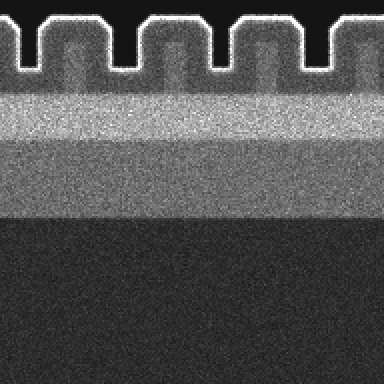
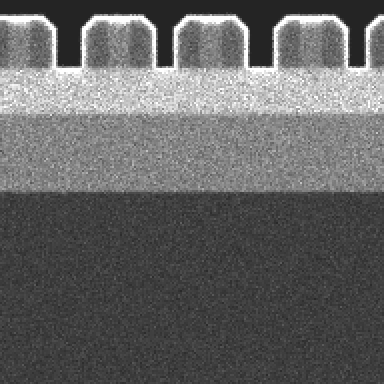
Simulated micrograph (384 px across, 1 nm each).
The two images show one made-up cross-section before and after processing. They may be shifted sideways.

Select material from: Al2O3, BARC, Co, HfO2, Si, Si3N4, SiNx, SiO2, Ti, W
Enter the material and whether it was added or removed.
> Si3N4 / removed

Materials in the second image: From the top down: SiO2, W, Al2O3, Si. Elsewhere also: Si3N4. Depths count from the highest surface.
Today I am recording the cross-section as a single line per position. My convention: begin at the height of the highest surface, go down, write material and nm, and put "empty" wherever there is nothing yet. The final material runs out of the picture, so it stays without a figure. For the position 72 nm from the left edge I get empty 52, W 46, Al2O3 78, Si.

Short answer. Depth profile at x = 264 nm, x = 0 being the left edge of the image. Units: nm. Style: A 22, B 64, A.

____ empty 52, W 46, Al2O3 78, Si